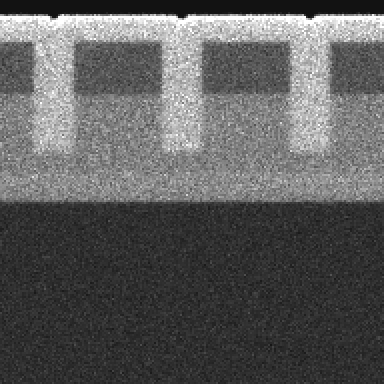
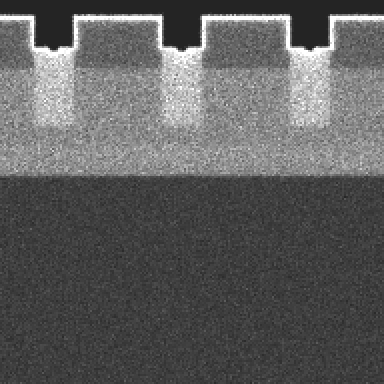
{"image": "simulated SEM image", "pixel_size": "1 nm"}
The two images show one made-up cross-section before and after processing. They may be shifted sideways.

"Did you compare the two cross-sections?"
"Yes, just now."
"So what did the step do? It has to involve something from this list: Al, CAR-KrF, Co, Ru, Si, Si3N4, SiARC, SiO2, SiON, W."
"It removed W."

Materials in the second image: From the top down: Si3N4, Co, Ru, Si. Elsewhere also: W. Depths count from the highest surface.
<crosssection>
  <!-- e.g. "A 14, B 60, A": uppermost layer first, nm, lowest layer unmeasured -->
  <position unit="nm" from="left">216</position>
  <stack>Si3N4 52, Co 78, Ru 30, Si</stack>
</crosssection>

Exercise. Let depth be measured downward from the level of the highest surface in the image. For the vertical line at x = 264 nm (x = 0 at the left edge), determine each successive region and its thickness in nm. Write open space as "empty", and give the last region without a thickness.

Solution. Si3N4 52, Co 78, Ru 30, Si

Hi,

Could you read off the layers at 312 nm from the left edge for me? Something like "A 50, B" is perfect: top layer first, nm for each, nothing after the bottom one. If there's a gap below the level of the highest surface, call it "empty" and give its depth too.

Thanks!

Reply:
empty 36, W 74, Co 20, Ru 30, Si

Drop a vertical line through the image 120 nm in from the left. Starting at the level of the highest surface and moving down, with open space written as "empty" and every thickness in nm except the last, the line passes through Si3N4 52, Co 78, Ru 30, Si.